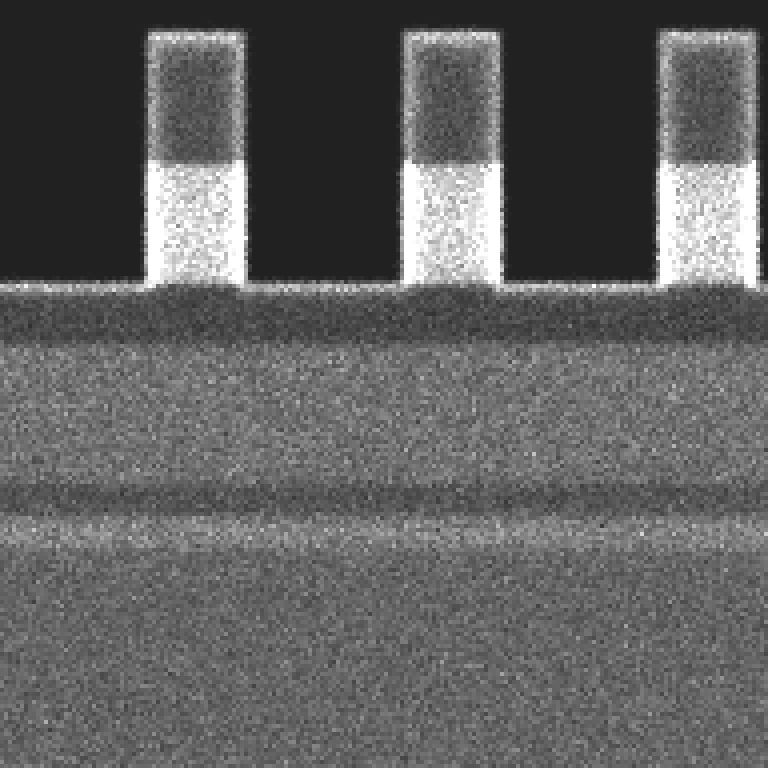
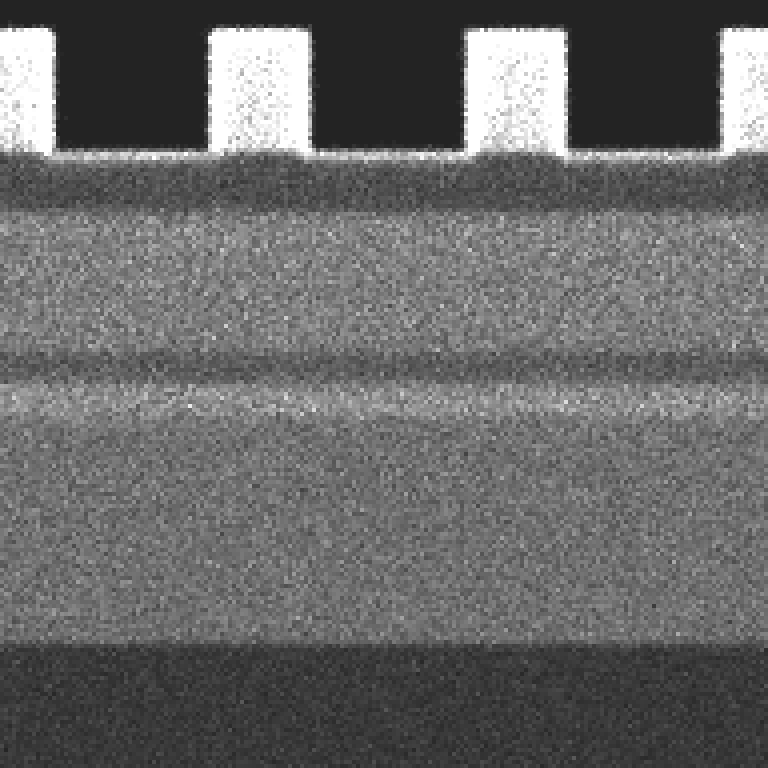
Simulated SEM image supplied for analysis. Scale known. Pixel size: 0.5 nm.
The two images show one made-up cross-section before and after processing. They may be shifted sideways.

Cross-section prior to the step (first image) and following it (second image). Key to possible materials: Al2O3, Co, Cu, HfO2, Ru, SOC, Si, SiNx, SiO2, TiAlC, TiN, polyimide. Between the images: SOC was removed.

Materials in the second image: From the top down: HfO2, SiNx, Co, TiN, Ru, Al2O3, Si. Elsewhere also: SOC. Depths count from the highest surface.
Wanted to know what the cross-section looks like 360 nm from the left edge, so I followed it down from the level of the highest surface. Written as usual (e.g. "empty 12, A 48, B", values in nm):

empty 60, SiNx 30, Co 70, TiN 16, Ru 16, Al2O3 114, Si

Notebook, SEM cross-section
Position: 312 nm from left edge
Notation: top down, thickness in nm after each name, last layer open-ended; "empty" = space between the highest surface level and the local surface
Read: empty 60, SiNx 30, Co 70, TiN 16, Ru 16, Al2O3 114, Si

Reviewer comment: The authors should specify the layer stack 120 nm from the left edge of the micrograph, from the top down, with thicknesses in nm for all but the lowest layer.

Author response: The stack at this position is HfO2 60, SiNx 30, Co 70, TiN 16, Ru 16, Al2O3 114, Si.